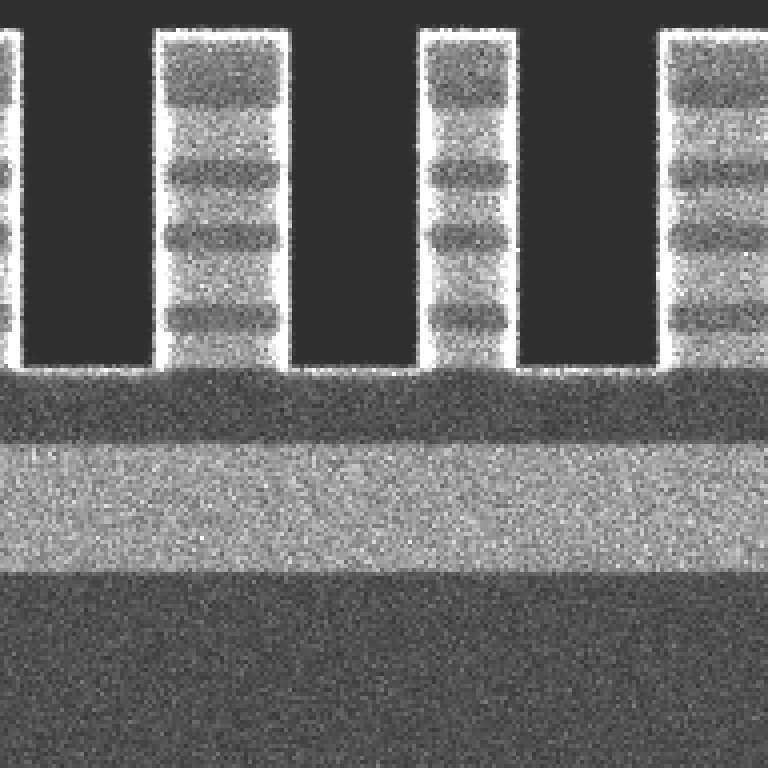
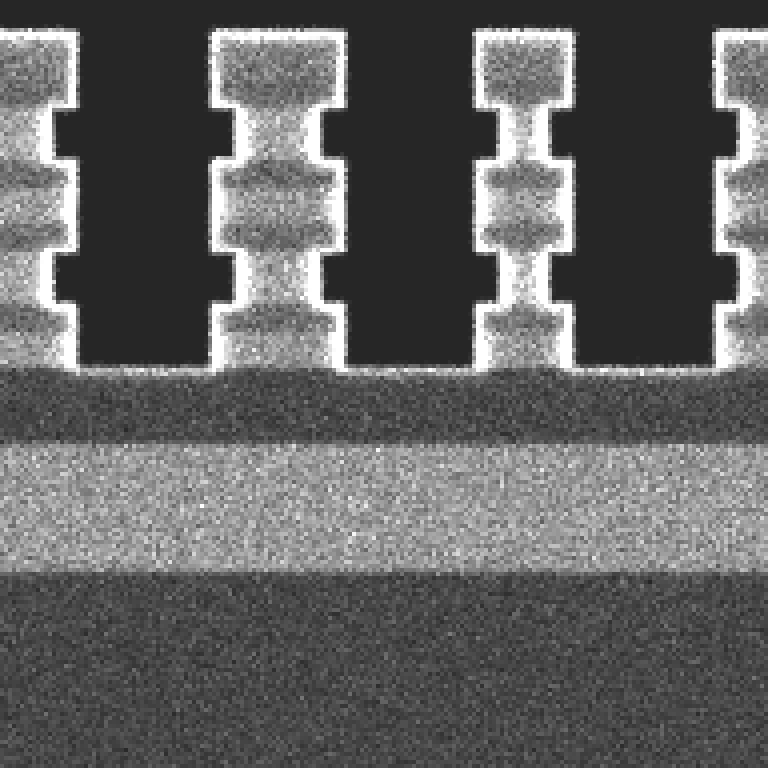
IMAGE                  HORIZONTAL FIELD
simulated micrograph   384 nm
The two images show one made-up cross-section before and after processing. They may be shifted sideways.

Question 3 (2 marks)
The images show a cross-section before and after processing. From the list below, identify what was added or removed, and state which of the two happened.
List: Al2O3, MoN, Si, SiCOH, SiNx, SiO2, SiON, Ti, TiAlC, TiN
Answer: Al2O3 was removed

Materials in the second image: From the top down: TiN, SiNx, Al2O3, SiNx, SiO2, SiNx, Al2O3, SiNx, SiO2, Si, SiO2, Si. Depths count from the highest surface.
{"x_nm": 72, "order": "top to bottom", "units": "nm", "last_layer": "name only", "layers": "empty 168, Si 38, SiO2 64, Si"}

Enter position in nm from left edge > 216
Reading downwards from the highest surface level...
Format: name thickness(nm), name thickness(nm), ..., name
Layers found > empty 168, Si 38, SiO2 64, Si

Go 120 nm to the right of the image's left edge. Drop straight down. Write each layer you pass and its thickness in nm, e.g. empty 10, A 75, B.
TiN 24, SiNx 14, Al2O3 26, SiNx 14, SiO2 18, SiNx 14, Al2O3 26, SiNx 14, SiO2 18, Si 38, SiO2 64, Si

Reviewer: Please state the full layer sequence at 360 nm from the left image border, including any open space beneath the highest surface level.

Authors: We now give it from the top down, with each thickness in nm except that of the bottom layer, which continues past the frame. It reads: TiN 24, SiNx 14, empty 26, SiNx 14, SiO2 18, SiNx 14, empty 26, SiNx 14, SiO2 18, Si 38, SiO2 64, Si